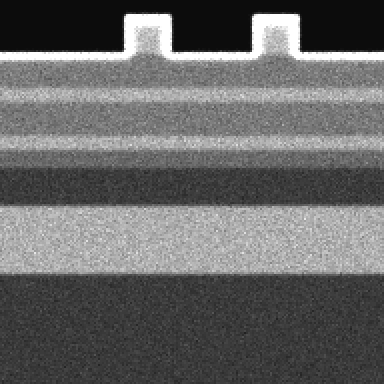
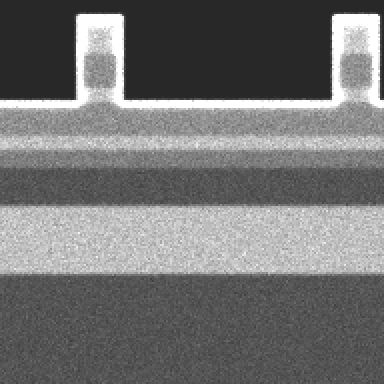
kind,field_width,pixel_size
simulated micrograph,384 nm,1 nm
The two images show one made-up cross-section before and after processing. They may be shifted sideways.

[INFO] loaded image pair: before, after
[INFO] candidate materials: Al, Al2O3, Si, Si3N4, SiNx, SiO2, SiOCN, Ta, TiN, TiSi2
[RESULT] removed Si3N4 and SiO2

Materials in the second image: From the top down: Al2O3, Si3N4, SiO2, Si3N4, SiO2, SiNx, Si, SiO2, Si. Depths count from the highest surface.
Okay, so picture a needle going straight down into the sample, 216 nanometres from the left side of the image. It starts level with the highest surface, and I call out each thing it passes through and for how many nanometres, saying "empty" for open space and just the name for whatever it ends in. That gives empty 86, Si3N4 34, SiO2 14, SiNx 18, Si 38, SiO2 68, Si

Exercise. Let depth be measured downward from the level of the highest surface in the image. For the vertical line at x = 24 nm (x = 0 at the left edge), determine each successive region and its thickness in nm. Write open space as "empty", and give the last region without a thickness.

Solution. empty 86, Si3N4 34, SiO2 14, SiNx 18, Si 38, SiO2 68, Si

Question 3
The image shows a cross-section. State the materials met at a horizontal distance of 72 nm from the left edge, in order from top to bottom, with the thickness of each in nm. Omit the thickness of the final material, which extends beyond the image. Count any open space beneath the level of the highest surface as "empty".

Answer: empty 86, Si3N4 34, SiO2 14, SiNx 18, Si 38, SiO2 68, Si